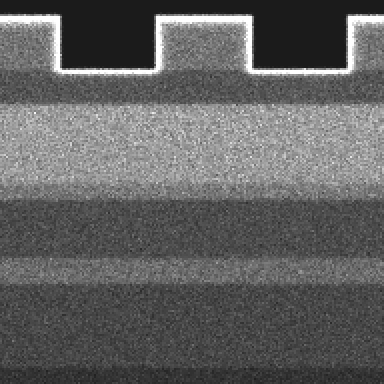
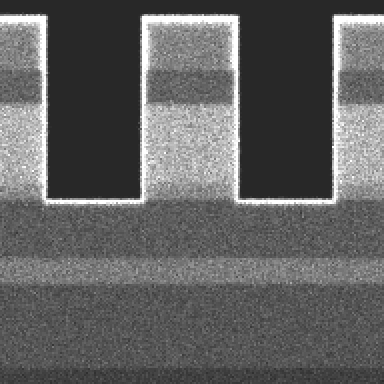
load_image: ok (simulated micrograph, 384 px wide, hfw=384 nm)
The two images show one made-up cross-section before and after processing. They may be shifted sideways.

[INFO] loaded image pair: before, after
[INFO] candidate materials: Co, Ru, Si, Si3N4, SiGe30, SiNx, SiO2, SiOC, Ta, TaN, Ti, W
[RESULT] removed Ru and Si3N4 and W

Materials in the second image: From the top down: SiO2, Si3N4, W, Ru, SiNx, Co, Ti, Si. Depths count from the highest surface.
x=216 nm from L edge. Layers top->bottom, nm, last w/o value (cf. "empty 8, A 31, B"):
SiO2 54, Si3N4 34, W 80, Ru 16, SiNx 58, Co 26, Ti 84, Si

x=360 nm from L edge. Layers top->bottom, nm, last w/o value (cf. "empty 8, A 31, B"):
SiO2 54, Si3N4 34, W 80, Ru 16, SiNx 58, Co 26, Ti 84, Si